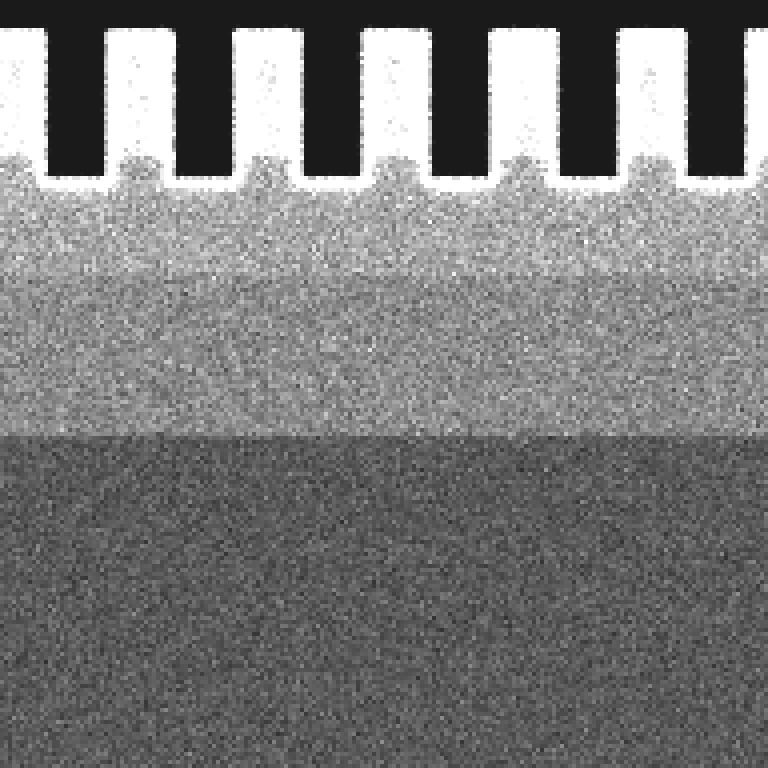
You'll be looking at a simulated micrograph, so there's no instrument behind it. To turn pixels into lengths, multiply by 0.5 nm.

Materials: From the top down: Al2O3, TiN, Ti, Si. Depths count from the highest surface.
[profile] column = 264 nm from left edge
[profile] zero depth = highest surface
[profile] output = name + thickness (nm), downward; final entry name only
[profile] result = Al2O3 62, TiN 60, Ti 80, Si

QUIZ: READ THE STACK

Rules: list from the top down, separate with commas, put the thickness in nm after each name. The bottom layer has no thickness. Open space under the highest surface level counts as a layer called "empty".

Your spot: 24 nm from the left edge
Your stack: empty 74, TiN 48, Ti 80, Si